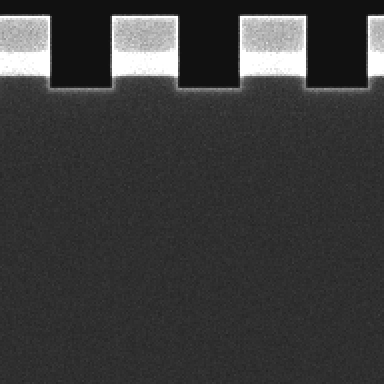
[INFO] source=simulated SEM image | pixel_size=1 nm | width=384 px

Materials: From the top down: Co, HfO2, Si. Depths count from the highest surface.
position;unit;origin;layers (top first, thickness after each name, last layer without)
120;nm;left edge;Co 36, HfO2 24, Si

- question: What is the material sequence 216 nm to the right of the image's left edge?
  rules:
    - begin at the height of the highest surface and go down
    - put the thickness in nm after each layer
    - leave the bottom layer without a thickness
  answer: empty 72, Si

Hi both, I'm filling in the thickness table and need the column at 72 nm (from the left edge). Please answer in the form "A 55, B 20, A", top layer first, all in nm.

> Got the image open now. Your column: empty 72, Si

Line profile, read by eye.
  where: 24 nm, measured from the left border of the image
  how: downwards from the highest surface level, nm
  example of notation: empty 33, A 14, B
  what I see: Co 36, HfO2 24, Si